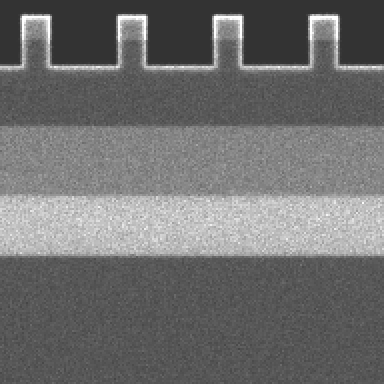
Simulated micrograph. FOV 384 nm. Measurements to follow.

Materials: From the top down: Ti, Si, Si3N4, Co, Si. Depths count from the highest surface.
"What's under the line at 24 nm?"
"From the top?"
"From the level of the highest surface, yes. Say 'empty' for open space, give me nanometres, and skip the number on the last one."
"Ti 24, Si 86, Si3N4 70, Co 60, Si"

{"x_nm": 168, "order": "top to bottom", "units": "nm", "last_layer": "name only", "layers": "empty 50, Si 60, Si3N4 70, Co 60, Si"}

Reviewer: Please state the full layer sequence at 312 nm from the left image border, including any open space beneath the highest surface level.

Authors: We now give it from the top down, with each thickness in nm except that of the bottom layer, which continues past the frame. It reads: Ti 24, Si 86, Si3N4 70, Co 60, Si